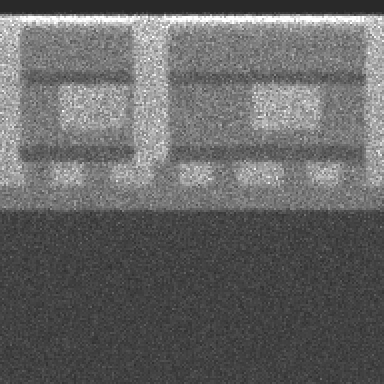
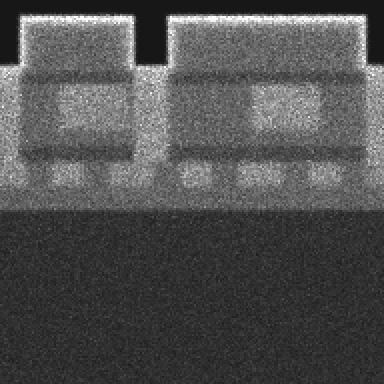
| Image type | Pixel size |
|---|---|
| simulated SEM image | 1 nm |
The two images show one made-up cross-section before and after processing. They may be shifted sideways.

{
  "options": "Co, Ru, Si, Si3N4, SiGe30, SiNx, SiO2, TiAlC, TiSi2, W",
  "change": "removed",
  "material": "Ru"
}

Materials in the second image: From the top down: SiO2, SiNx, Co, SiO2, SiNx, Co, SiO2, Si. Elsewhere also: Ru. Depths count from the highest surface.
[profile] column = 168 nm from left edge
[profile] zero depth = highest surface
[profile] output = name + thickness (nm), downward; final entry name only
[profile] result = SiO2 56, SiNx 12, SiO2 62, SiNx 16, SiO2 48, Si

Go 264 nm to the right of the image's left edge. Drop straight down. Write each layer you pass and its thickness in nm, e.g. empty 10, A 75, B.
SiO2 56, SiNx 12, Co 46, SiO2 16, SiNx 16, Co 24, SiO2 24, Si